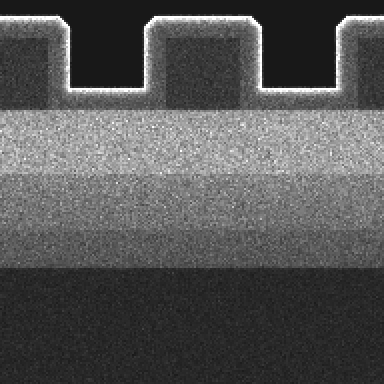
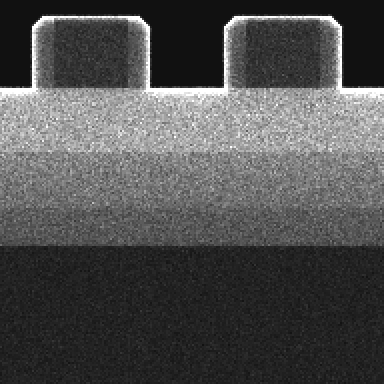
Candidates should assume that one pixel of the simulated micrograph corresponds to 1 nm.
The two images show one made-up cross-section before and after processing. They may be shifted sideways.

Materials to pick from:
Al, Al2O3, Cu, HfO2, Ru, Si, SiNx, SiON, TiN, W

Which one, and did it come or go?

Al2O3 - removed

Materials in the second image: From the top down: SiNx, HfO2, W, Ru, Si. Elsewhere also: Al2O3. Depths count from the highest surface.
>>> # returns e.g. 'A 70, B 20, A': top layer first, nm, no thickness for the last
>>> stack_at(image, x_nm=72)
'SiNx 72, HfO2 64, W 56, Ru 38, Si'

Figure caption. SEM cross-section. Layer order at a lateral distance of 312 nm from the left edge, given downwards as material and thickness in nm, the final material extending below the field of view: SiNx 72, HfO2 64, W 56, Ru 38, Si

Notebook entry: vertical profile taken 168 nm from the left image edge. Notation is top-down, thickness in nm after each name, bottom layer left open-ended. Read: empty 72, HfO2 64, W 56, Ru 38, Si